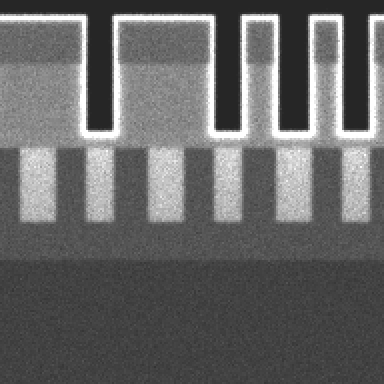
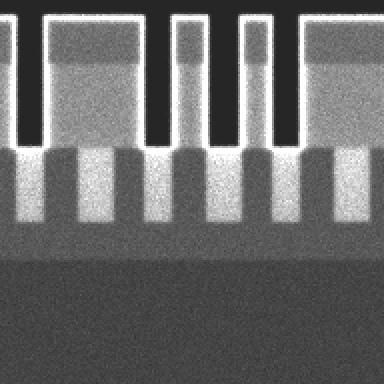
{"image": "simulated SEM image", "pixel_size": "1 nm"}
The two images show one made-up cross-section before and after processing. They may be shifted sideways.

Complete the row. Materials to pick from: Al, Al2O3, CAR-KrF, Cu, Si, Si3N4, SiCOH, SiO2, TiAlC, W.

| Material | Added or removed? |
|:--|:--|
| Al2O3 | removed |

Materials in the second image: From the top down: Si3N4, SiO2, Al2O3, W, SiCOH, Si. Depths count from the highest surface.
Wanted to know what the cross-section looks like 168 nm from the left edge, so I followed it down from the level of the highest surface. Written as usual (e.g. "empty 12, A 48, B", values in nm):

empty 132, W 74, SiCOH 38, Si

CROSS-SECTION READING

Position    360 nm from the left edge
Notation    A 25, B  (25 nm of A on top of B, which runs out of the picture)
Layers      Si3N4 48, SiO2 68, Al2O3 16, W 74, SiCOH 38, Si